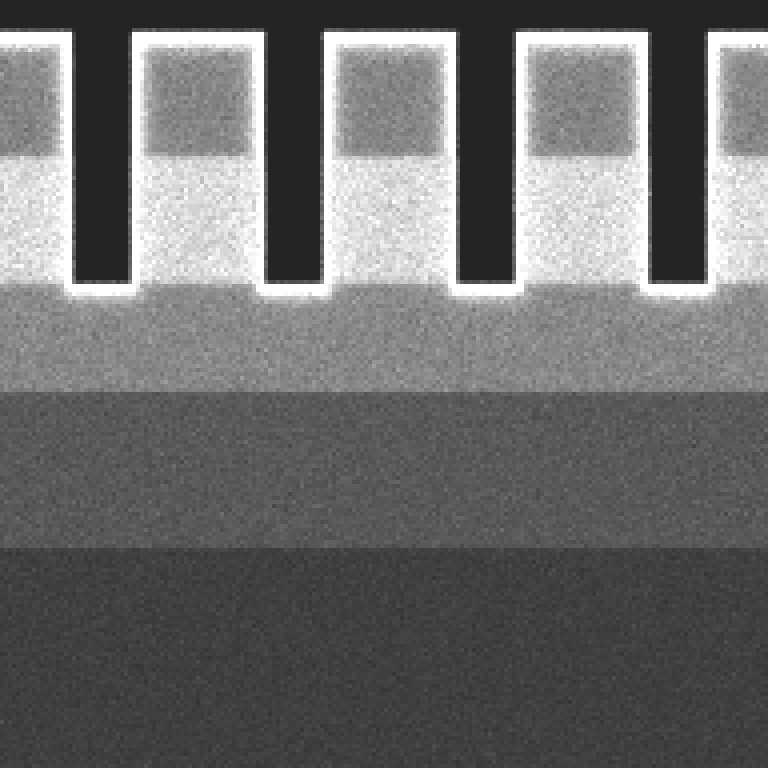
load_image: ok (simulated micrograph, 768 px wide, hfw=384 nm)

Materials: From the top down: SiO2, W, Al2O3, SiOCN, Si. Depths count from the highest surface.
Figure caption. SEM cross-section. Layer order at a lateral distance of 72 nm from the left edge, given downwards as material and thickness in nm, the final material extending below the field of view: SiO2 62, W 64, Al2O3 54, SiOCN 78, Si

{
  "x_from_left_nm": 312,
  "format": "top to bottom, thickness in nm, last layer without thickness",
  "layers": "SiO2 62, W 64, Al2O3 54, SiOCN 78, Si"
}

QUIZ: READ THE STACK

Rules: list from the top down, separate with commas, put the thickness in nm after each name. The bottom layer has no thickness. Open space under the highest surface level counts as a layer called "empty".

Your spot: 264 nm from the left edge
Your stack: SiO2 62, W 64, Al2O3 54, SiOCN 78, Si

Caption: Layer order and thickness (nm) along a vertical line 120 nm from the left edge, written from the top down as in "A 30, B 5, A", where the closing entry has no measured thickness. SiO2 62, W 64, Al2O3 54, SiOCN 78, Si